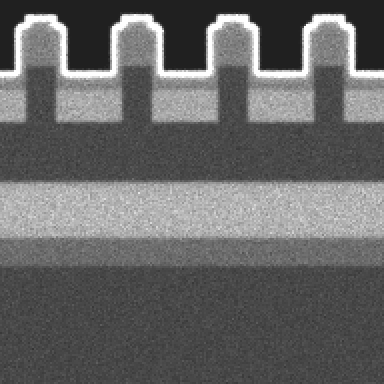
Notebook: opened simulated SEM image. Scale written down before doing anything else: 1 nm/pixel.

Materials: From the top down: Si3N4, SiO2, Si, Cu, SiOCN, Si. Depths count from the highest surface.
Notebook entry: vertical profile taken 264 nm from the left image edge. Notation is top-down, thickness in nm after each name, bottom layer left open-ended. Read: empty 56, Si3N4 18, SiO2 32, Si 60, Cu 56, SiOCN 28, Si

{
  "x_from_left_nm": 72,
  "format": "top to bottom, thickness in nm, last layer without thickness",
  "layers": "empty 56, Si3N4 18, SiO2 32, Si 60, Cu 56, SiOCN 28, Si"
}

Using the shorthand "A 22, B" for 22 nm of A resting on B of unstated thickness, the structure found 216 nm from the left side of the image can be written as empty 8, Si3N4 66, SiO2 32, Si 60, Cu 56, SiOCN 28, Si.